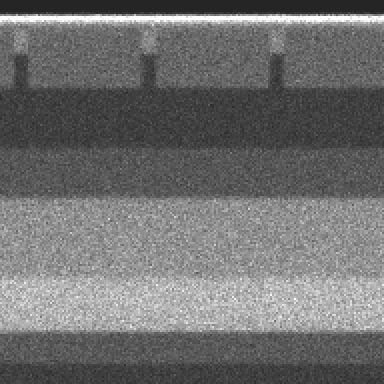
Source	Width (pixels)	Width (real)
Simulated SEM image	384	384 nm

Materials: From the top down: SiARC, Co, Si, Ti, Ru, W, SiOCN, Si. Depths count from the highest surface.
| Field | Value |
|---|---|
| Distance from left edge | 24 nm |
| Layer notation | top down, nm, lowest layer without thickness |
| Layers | SiARC 14, Co 24, Si 94, Ti 50, Ru 80, W 54, SiOCN 32, Si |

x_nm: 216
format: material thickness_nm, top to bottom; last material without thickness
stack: SiARC 72, Si 60, Ti 50, Ru 80, W 54, SiOCN 32, Si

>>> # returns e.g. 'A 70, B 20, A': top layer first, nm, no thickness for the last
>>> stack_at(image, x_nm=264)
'SiARC 72, Si 60, Ti 50, Ru 80, W 54, SiOCN 32, Si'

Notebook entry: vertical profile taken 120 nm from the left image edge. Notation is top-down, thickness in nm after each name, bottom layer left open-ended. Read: SiARC 72, Si 60, Ti 50, Ru 80, W 54, SiOCN 32, Si